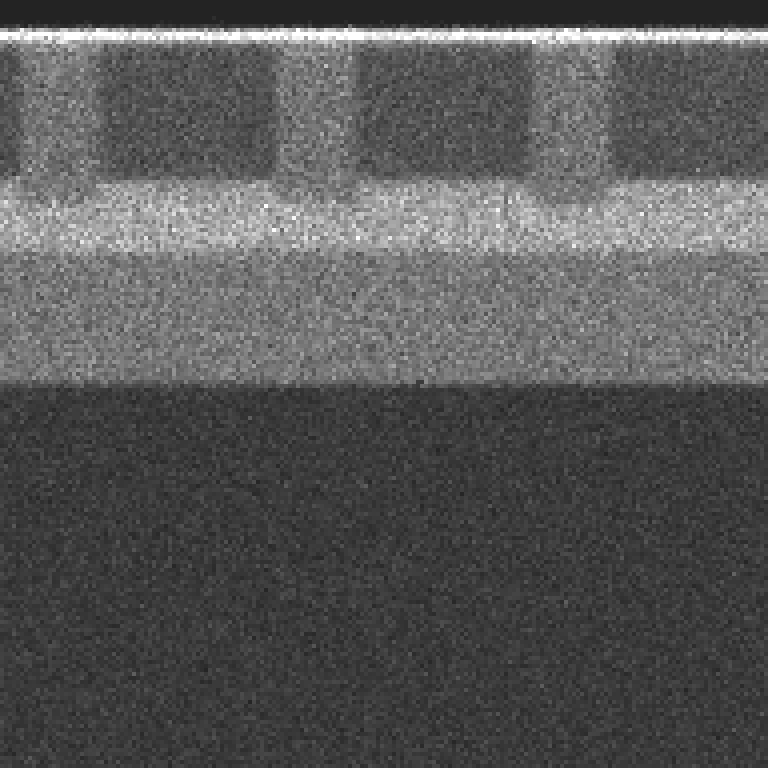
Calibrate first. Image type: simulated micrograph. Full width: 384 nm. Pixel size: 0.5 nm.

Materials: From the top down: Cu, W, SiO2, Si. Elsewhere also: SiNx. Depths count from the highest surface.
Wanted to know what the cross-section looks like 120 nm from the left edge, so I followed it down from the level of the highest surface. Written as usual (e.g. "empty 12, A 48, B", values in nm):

SiNx 74, W 36, SiO2 66, Si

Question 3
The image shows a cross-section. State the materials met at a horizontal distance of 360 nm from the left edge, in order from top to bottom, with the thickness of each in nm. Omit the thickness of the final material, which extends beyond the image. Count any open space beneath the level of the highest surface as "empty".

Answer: SiNx 74, W 36, SiO2 66, Si